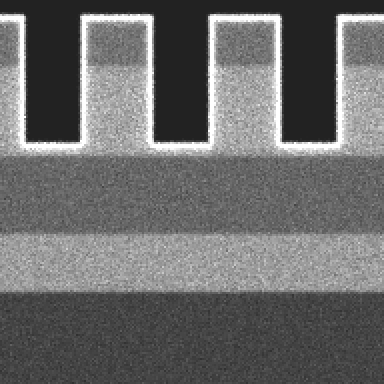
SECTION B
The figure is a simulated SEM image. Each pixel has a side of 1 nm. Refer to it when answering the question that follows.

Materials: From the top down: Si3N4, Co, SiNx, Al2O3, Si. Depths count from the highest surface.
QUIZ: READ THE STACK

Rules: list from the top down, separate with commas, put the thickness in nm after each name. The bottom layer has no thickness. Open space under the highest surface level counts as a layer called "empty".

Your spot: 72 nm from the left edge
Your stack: empty 128, Co 12, SiNx 78, Al2O3 58, Si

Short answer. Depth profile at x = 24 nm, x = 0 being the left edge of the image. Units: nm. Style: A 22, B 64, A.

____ empty 128, Co 12, SiNx 78, Al2O3 58, Si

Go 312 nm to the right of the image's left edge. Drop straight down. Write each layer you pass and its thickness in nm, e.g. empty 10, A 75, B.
empty 128, Co 12, SiNx 78, Al2O3 58, Si